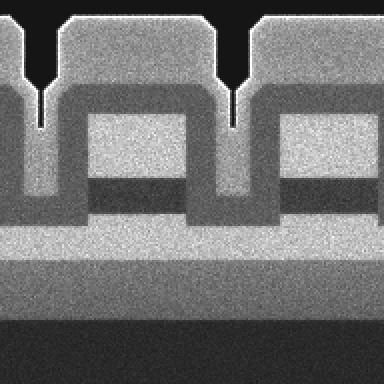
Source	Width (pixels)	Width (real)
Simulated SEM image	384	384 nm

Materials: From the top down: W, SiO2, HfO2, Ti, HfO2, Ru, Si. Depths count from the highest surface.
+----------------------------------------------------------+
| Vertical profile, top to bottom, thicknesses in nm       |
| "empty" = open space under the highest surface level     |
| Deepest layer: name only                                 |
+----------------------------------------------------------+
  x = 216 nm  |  empty 62, W 118, SiO2 30, HfO2 34, Ru 60, Si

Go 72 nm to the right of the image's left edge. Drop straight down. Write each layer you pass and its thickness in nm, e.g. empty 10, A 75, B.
W 68, SiO2 142, HfO2 34, Ru 60, Si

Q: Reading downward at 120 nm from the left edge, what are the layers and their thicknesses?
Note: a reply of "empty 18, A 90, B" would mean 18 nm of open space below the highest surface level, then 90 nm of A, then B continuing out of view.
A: W 68, SiO2 30, HfO2 64, Ti 36, HfO2 46, Ru 60, Si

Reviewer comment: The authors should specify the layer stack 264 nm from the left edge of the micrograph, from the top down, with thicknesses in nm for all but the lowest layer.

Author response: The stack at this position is W 68, SiO2 142, HfO2 34, Ru 60, Si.